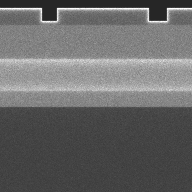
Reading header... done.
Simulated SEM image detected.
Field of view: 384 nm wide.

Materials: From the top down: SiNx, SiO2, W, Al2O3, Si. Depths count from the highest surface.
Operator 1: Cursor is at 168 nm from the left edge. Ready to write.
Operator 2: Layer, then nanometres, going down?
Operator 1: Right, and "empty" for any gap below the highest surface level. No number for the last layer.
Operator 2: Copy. SiNx 34, SiO2 68, W 64, Al2O3 32, Si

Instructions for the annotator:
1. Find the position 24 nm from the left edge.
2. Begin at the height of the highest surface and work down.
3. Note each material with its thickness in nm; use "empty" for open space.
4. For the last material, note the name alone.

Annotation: SiNx 34, SiO2 68, W 64, Al2O3 32, Si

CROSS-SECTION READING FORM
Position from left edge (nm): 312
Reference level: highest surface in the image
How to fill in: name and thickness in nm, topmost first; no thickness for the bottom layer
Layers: empty 26, SiNx 8, SiO2 68, W 64, Al2O3 32, Si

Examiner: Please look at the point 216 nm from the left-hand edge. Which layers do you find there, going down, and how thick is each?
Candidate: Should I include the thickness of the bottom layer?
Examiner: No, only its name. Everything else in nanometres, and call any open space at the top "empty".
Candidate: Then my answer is SiNx 34, SiO2 68, W 64, Al2O3 32, Si